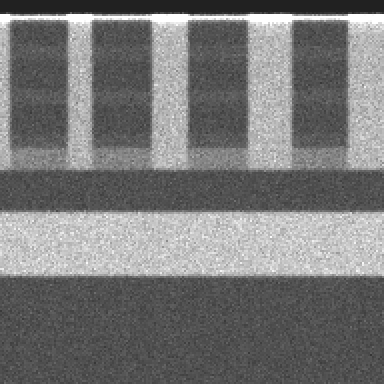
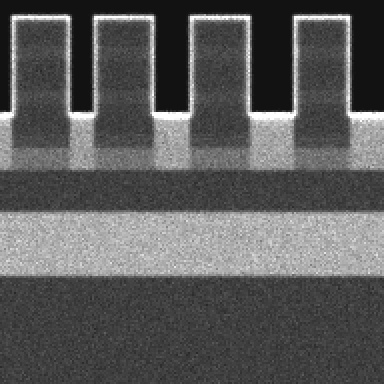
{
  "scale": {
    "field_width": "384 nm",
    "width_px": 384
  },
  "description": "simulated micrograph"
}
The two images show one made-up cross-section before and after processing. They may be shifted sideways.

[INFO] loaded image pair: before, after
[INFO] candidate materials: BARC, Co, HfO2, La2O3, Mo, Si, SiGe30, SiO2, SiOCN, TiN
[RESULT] removed Co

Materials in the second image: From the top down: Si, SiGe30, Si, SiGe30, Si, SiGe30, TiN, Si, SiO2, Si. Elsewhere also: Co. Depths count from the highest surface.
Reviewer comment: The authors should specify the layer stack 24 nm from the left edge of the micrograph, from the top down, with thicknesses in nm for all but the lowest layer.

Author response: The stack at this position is Si 30, SiGe30 14, Si 30, SiGe30 14, Si 30, SiGe30 14, TiN 22, Si 42, SiO2 64, Si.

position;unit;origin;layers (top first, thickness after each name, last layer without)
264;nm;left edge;empty 98, Co 56, Si 42, SiO2 64, Si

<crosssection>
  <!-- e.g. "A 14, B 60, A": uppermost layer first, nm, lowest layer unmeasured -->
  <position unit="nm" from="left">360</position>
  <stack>empty 98, Co 56, Si 42, SiO2 64, Si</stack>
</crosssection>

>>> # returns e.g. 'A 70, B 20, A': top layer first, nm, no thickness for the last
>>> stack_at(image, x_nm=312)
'Si 30, SiGe30 14, Si 30, SiGe30 14, Si 30, SiGe30 14, TiN 22, Si 42, SiO2 64, Si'